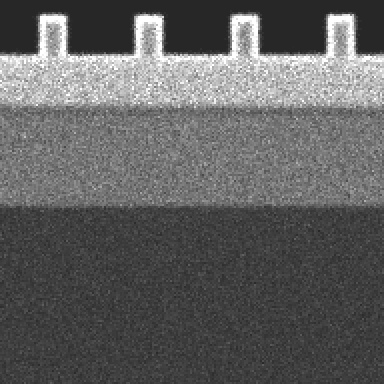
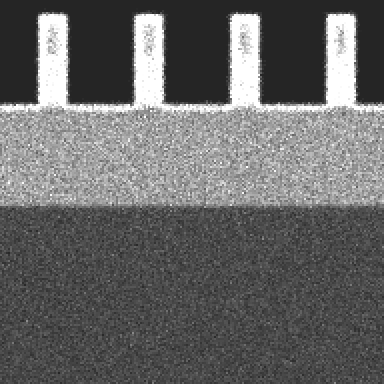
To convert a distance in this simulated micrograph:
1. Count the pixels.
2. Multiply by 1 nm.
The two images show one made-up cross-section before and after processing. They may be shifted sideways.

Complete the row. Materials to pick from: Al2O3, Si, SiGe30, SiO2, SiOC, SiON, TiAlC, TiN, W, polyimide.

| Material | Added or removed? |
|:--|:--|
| W | removed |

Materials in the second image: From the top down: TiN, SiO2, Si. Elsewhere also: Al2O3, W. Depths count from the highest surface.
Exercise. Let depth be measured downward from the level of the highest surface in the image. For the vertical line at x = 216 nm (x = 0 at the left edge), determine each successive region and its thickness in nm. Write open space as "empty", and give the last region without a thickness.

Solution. empty 90, TiN 10, SiO2 90, Si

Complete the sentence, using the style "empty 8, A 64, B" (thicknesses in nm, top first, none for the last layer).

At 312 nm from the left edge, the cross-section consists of empty 90, TiN 10, SiO2 90, Si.